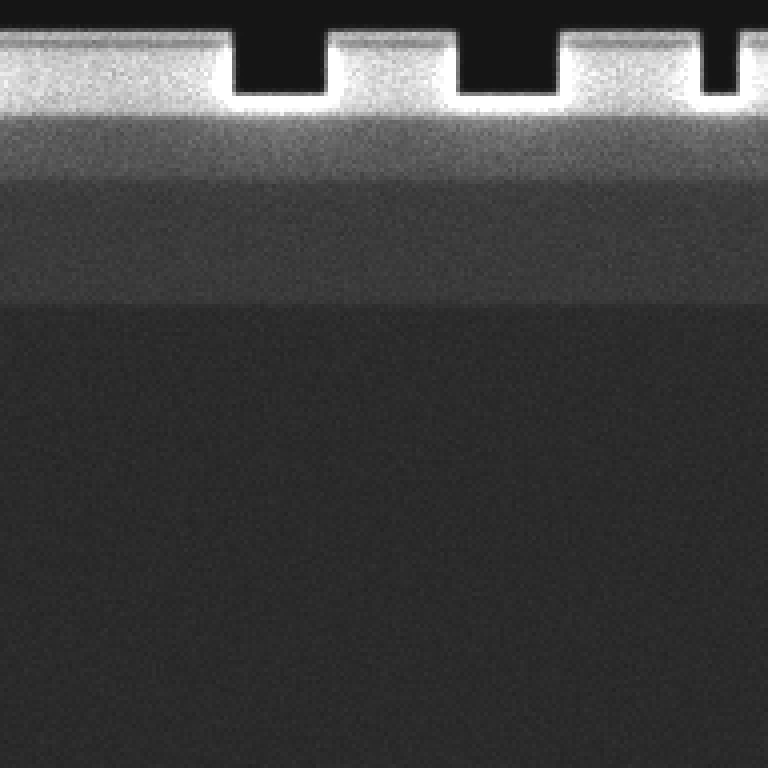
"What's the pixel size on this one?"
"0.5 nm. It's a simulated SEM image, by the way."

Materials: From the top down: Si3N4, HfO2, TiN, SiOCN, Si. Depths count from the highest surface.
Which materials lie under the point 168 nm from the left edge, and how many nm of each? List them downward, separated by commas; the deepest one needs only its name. Si3N4 8, HfO2 34, TiN 32, SiOCN 62, Si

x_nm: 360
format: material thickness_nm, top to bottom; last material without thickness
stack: empty 32, HfO2 10, TiN 32, SiOCN 62, Si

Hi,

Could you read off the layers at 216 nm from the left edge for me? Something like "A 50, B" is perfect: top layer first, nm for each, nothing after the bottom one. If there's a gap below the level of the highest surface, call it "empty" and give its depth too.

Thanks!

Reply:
Si3N4 8, HfO2 34, TiN 32, SiOCN 62, Si